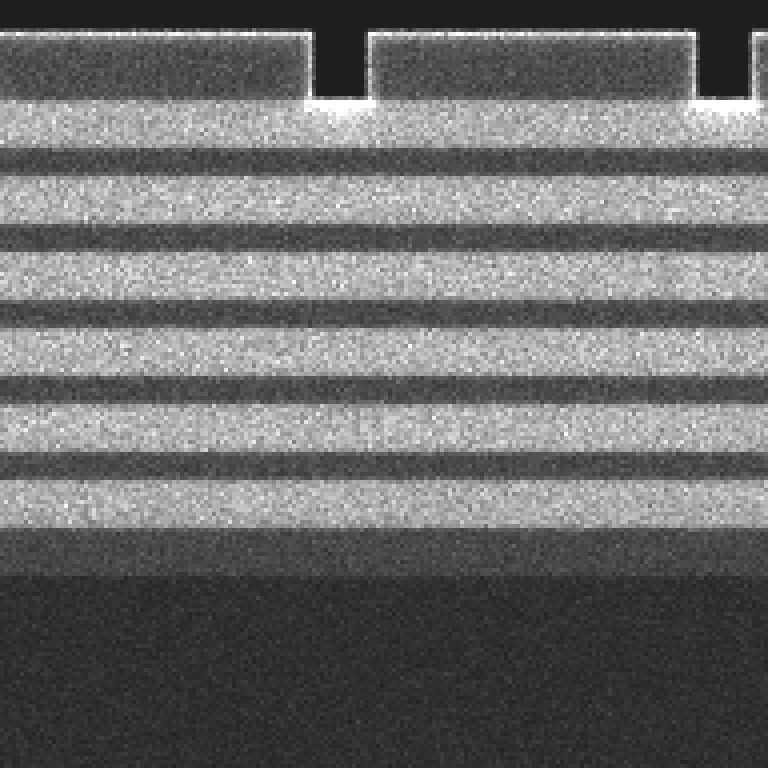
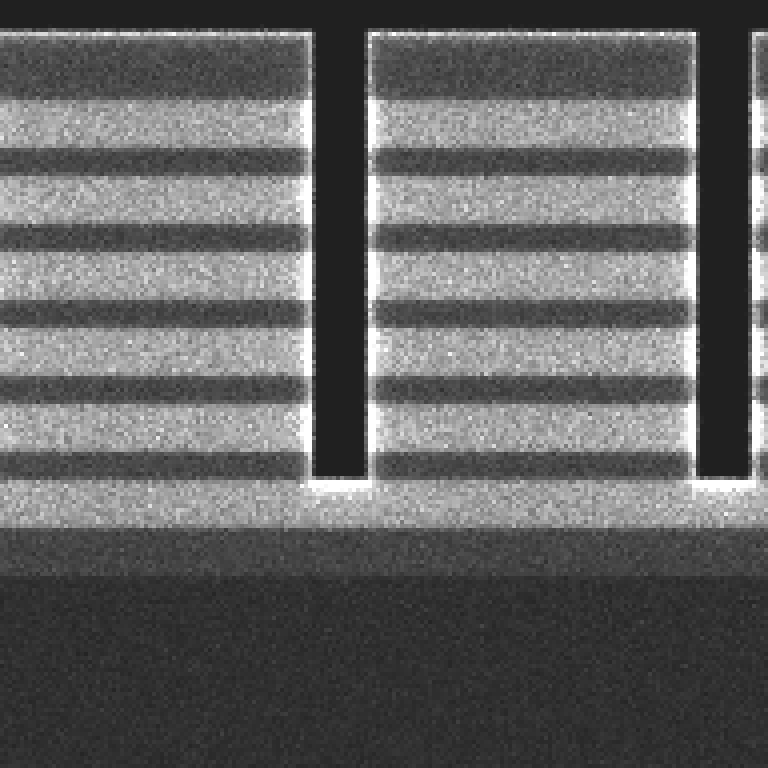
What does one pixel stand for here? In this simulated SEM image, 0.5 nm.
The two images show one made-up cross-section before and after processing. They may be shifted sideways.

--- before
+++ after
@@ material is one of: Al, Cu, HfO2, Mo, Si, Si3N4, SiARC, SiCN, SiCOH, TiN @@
HfO2 and Si3N4 removed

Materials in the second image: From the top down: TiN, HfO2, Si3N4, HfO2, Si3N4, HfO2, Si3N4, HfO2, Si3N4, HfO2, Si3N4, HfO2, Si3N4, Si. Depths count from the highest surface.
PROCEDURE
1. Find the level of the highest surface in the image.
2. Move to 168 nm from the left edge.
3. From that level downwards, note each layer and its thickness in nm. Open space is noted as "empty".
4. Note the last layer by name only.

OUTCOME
empty 224, HfO2 24, Si3N4 24, Si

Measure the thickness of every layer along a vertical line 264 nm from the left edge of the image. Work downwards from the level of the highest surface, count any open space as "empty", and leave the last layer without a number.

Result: TiN 34, HfO2 24, Si3N4 14, HfO2 24, Si3N4 14, HfO2 24, Si3N4 14, HfO2 24, Si3N4 14, HfO2 24, Si3N4 14, HfO2 24, Si3N4 24, Si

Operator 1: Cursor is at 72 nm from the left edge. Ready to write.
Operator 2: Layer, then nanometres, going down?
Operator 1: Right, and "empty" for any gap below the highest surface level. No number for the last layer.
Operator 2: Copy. TiN 34, HfO2 24, Si3N4 14, HfO2 24, Si3N4 14, HfO2 24, Si3N4 14, HfO2 24, Si3N4 14, HfO2 24, Si3N4 14, HfO2 24, Si3N4 24, Si